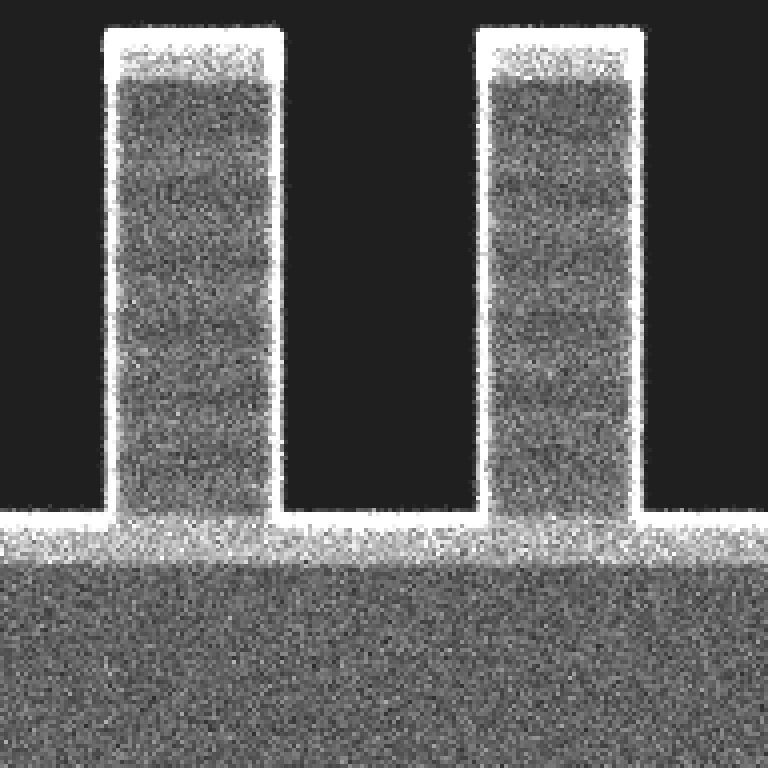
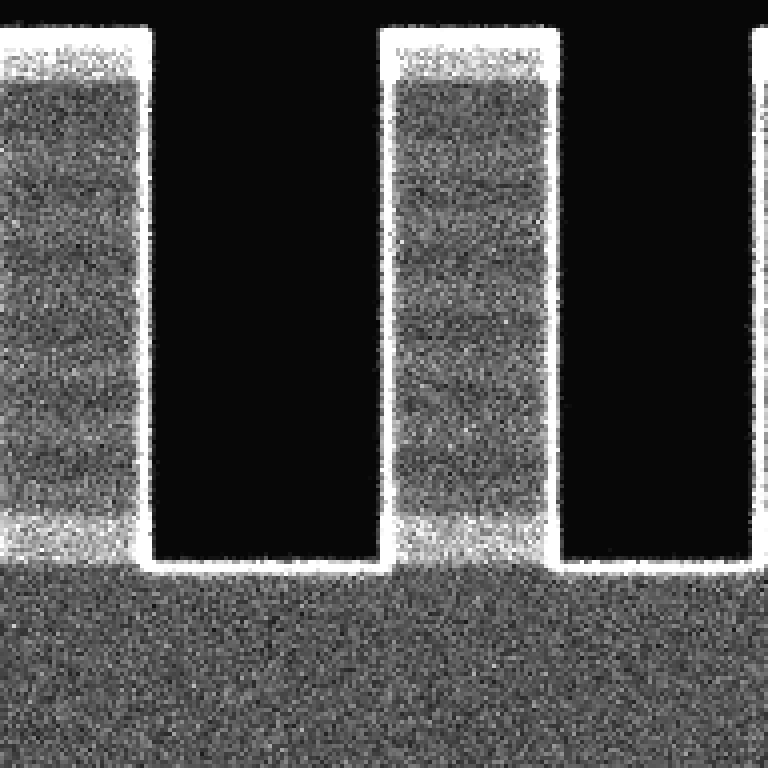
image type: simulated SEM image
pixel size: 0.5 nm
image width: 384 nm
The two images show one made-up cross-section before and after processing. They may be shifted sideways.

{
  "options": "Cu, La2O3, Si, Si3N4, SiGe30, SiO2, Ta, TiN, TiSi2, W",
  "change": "removed",
  "material": "TiN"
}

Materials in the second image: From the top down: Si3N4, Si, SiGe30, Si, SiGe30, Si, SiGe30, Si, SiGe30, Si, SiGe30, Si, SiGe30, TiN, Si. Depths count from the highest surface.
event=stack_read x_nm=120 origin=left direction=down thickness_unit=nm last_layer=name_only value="empty 266, Si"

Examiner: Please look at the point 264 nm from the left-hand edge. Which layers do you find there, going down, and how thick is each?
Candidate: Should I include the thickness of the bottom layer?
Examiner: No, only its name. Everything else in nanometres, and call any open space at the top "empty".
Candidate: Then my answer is Si3N4 24, Si 30, SiGe30 18, Si 16, SiGe30 18, Si 16, SiGe30 18, Si 16, SiGe30 18, Si 16, SiGe30 18, Si 16, SiGe30 18, TiN 24, Si